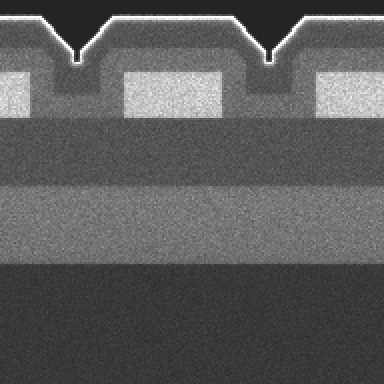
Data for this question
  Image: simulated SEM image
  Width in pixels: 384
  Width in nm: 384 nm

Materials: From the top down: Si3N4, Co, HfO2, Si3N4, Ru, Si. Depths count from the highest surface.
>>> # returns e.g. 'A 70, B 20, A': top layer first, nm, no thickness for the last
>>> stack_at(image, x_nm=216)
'Si3N4 32, Co 24, HfO2 46, Si3N4 68, Ru 78, Si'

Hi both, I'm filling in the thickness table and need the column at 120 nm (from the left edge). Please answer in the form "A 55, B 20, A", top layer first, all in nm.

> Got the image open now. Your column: Si3N4 32, Co 70, Si3N4 68, Ru 78, Si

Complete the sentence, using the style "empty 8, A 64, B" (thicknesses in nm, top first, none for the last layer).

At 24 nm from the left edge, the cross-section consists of Si3N4 32, Co 24, HfO2 46, Si3N4 68, Ru 78, Si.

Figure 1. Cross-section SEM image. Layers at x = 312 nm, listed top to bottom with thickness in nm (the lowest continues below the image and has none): Si3N4 32, Co 70, Si3N4 68, Ru 78, Si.